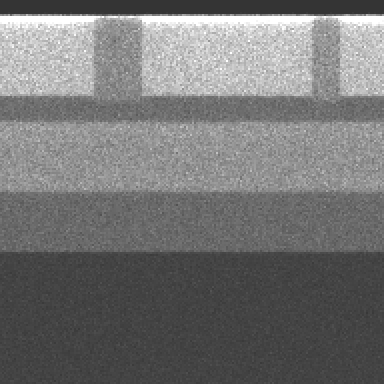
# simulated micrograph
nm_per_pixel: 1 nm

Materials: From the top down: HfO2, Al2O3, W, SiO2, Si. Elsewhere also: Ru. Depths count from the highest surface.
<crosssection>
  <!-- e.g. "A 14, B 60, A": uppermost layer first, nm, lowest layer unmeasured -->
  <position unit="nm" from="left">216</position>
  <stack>HfO2 80, Al2O3 26, W 70, SiO2 60, Si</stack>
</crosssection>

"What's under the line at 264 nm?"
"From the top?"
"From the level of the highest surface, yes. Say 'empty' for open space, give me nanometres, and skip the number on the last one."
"HfO2 80, Al2O3 26, W 70, SiO2 60, Si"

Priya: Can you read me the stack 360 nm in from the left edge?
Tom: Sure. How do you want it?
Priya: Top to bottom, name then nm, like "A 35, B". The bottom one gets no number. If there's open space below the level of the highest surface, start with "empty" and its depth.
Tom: HfO2 80, Al2O3 26, W 70, SiO2 60, Si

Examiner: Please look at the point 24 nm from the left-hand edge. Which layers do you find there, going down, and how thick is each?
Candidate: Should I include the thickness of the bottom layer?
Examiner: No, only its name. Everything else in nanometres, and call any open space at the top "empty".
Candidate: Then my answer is HfO2 80, Al2O3 26, W 70, SiO2 60, Si